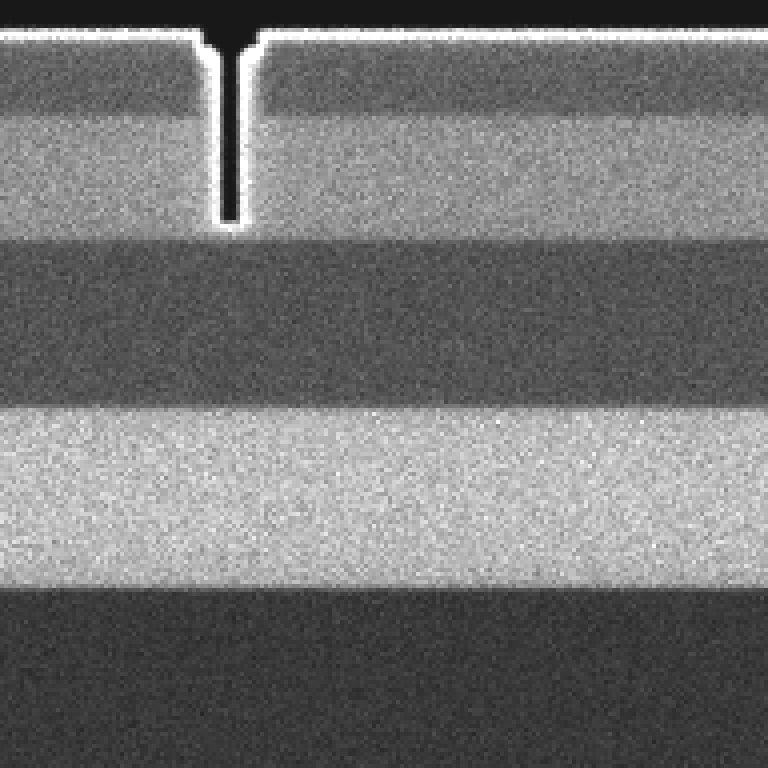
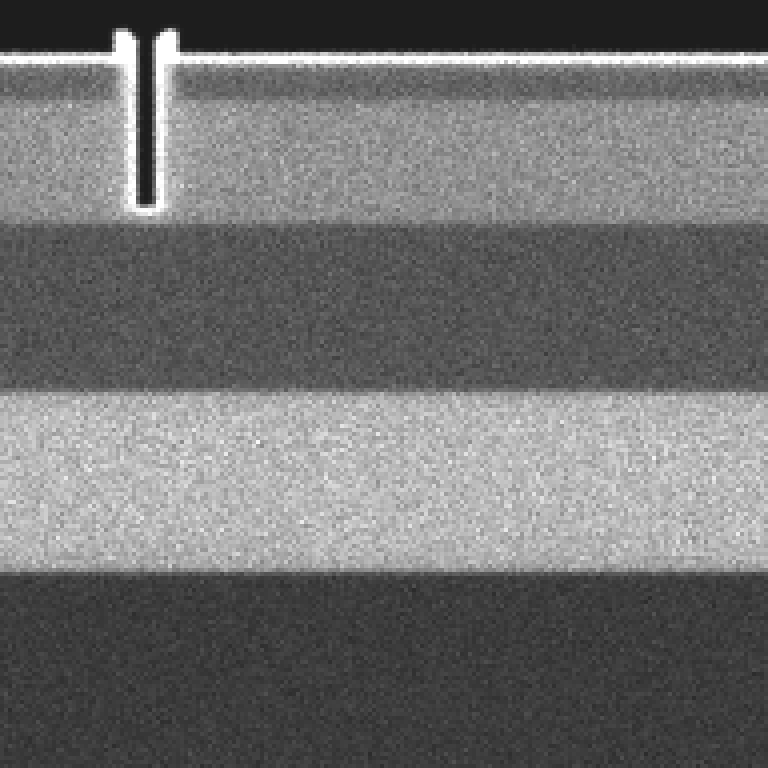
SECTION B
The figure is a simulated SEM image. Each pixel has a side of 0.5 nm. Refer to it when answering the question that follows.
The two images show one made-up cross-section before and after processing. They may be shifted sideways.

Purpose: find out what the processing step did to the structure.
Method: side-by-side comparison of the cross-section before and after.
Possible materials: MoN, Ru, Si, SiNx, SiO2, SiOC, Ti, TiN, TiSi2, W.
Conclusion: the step removed TiN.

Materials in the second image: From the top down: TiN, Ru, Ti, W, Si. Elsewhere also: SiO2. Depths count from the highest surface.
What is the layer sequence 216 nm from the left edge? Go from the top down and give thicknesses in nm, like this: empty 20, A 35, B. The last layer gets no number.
empty 12, TiN 22, Ru 62, Ti 84, W 90, Si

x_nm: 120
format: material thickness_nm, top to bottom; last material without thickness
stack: empty 12, TiN 22, Ru 62, Ti 84, W 90, Si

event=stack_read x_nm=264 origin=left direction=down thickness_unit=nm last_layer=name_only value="empty 12, TiN 22, Ru 62, Ti 84, W 90, Si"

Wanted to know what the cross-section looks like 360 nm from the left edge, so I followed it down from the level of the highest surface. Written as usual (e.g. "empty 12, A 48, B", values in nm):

empty 12, TiN 22, Ru 62, Ti 84, W 90, Si